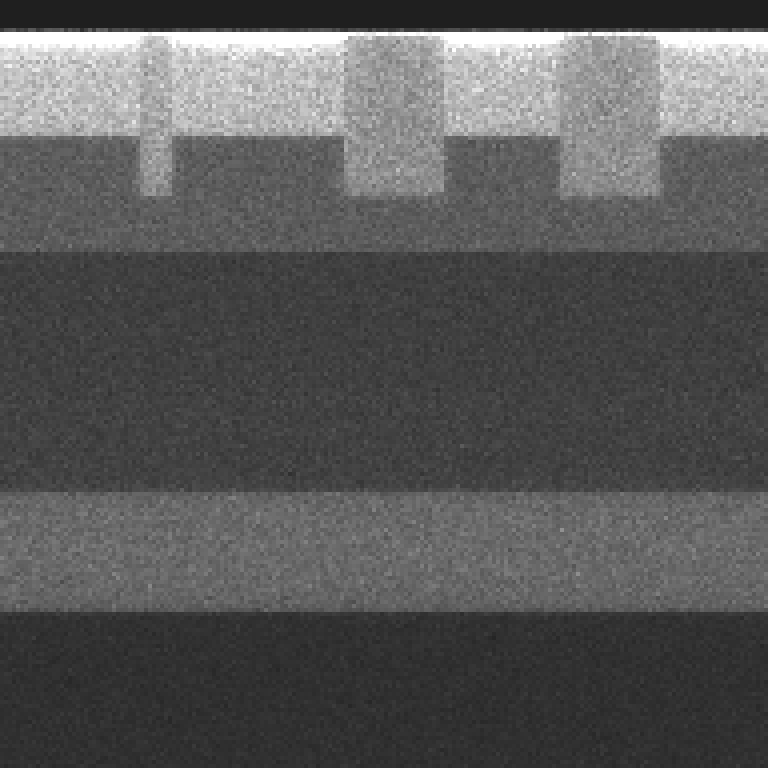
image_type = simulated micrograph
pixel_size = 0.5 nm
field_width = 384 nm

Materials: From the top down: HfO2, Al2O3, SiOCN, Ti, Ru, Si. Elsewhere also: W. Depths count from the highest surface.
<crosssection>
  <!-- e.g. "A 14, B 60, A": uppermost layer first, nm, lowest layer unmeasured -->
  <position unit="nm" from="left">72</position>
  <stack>W 82, Al2O3 28, SiOCN 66, Ti 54, Ru 60, Si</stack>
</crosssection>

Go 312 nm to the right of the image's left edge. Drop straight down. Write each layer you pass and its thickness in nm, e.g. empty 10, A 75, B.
W 82, Al2O3 28, SiOCN 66, Ti 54, Ru 60, Si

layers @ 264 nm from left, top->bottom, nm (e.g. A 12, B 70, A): HfO2 52, Al2O3 58, SiOCN 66, Ti 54, Ru 60, Si